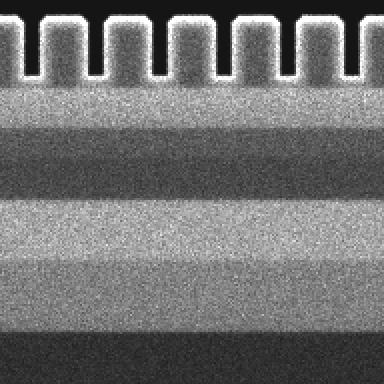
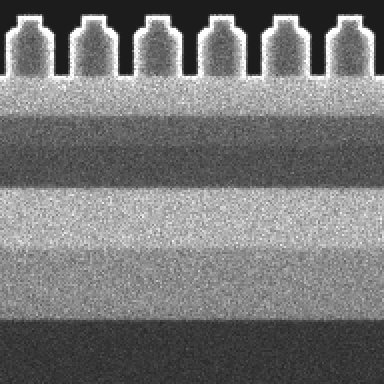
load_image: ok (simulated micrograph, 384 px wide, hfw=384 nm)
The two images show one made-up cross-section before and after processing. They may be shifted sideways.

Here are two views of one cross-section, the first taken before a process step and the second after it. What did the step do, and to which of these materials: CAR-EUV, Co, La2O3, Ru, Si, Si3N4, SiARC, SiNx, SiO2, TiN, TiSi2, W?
It removed SiO2.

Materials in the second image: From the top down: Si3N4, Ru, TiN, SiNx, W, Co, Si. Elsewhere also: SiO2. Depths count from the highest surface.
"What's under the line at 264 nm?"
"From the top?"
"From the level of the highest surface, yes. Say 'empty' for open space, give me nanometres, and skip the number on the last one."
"empty 16, SiO2 44, Ru 40, TiN 30, SiNx 42, W 60, Co 72, Si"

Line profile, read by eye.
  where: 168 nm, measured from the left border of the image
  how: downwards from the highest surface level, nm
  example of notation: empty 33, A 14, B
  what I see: Si3N4 60, Ru 40, TiN 30, SiNx 42, W 60, Co 72, Si